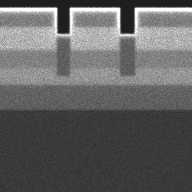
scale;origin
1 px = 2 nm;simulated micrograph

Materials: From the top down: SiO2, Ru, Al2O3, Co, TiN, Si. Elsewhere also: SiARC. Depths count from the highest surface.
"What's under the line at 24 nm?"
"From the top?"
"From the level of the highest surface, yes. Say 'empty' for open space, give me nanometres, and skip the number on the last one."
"SiO2 38, Ru 46, Al2O3 36, Co 34, TiN 50, Si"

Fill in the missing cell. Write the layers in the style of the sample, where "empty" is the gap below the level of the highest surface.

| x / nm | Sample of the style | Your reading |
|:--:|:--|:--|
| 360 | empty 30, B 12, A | SiO2 38, Ru 46, Al2O3 36, Co 34, TiN 50, Si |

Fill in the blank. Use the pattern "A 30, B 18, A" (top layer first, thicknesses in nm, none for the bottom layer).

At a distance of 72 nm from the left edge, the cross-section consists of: SiO2 38, Ru 46, Al2O3 36, Co 34, TiN 50, Si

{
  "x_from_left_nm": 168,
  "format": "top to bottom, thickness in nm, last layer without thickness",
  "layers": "SiO2 38, Ru 46, Al2O3 36, Co 34, TiN 50, Si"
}